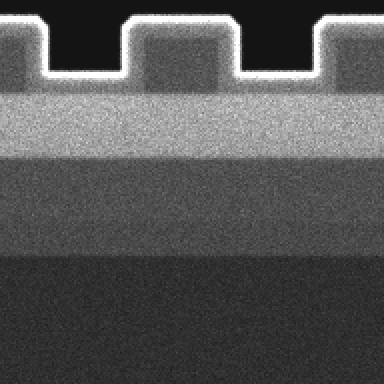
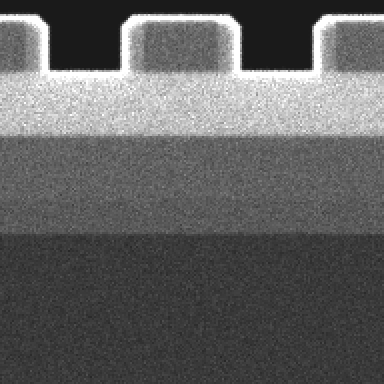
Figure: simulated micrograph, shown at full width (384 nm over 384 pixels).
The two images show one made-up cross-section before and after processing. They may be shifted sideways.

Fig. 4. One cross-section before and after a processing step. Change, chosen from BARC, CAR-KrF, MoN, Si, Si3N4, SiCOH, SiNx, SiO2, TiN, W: SiO2 removed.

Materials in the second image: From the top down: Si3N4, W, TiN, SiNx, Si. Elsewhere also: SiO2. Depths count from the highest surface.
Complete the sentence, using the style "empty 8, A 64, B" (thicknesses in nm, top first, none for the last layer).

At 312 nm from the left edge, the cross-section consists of empty 56, W 64, TiN 64, SiNx 34, Si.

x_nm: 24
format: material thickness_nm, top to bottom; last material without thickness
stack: Si3N4 56, W 64, TiN 64, SiNx 34, Si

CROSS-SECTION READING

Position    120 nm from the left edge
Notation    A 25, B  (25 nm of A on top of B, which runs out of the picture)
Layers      empty 56, W 64, TiN 64, SiNx 34, Si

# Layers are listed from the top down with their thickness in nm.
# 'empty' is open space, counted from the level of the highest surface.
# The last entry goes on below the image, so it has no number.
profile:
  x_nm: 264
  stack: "empty 56, W 64, TiN 64, SiNx 34, Si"